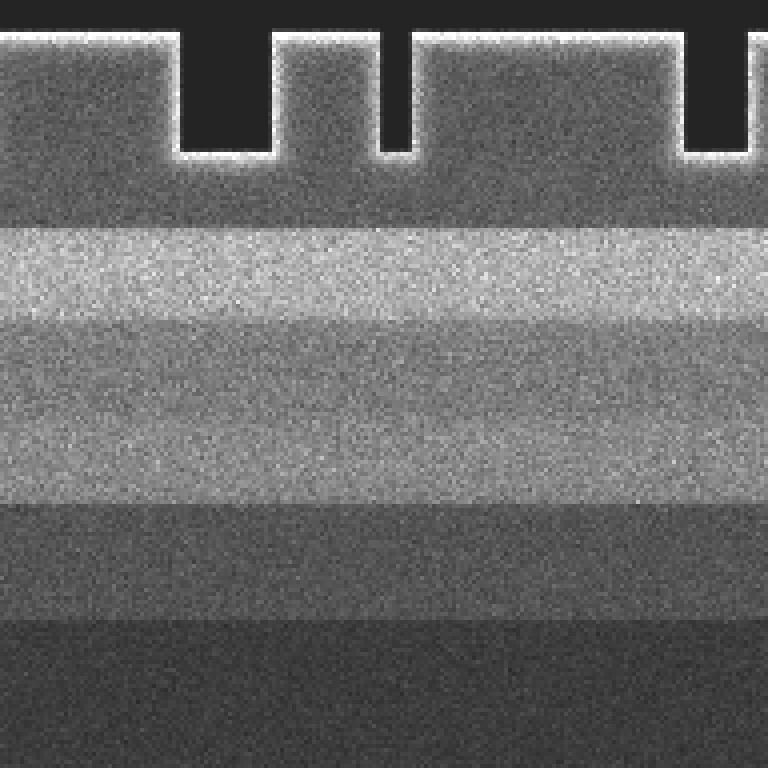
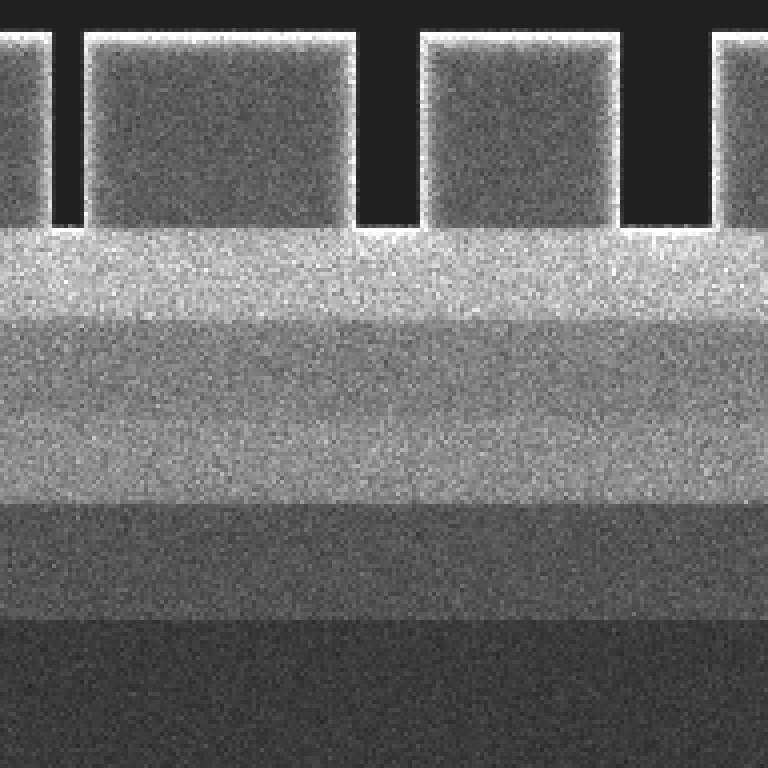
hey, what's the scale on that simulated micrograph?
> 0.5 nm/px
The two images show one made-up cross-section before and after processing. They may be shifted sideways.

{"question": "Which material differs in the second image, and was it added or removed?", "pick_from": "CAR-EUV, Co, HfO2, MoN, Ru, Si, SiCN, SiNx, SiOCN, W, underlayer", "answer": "underlayer, removed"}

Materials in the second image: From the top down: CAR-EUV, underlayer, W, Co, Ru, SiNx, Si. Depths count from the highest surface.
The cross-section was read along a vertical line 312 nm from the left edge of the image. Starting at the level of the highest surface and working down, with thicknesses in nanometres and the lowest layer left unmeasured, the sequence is empty 98, W 46, Co 50, Ru 42, SiNx 58, Si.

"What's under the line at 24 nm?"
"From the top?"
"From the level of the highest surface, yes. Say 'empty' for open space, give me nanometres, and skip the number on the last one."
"CAR-EUV 60, underlayer 38, W 46, Co 50, Ru 42, SiNx 58, Si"